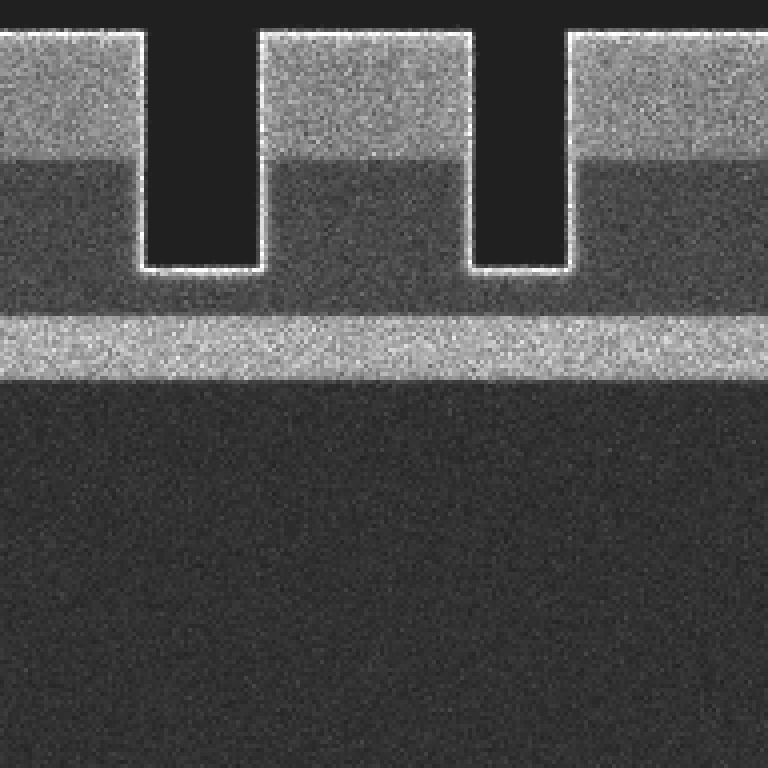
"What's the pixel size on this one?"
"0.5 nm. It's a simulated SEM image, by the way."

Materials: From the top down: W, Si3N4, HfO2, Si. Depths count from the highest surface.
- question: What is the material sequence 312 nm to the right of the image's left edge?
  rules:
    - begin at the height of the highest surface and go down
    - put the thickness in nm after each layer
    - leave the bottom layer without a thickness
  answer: W 64, Si3N4 78, HfO2 32, Si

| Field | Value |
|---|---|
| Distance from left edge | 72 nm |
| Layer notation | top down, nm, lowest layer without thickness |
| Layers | empty 118, Si3N4 24, HfO2 32, Si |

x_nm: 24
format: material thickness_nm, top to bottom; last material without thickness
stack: W 64, Si3N4 78, HfO2 32, Si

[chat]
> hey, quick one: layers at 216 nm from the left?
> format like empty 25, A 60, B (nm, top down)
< W 64, Si3N4 78, HfO2 32, Si